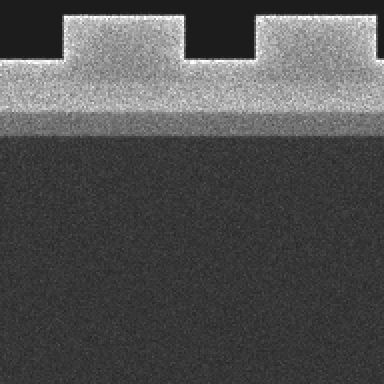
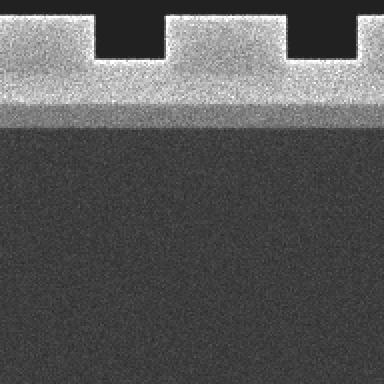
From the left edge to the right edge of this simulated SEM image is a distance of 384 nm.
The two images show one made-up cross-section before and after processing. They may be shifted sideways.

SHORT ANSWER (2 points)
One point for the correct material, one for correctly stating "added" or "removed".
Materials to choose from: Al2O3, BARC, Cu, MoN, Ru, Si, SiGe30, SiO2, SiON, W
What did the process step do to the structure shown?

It removed Ru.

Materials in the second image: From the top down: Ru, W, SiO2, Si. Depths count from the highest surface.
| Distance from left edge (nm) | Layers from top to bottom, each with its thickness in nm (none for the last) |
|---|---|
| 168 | Ru 58, W 30, SiO2 24, Si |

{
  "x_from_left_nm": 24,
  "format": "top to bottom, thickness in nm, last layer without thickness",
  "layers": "Ru 58, W 30, SiO2 24, Si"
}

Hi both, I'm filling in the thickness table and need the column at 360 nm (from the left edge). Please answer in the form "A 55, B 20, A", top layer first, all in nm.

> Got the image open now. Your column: Ru 58, W 30, SiO2 24, Si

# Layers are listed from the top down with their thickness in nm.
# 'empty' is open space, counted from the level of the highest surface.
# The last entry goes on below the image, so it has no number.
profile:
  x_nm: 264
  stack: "Ru 58, W 30, SiO2 24, Si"